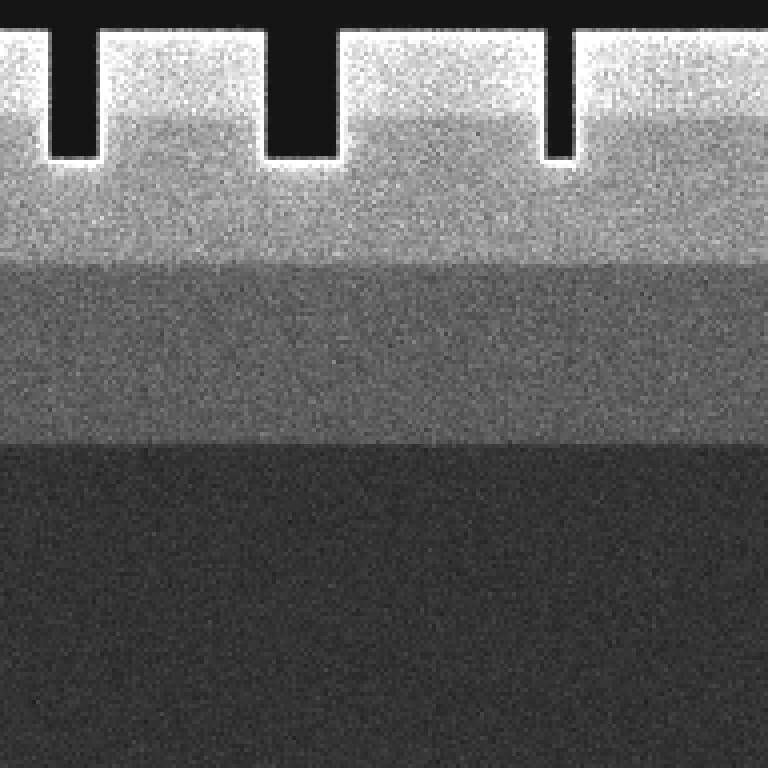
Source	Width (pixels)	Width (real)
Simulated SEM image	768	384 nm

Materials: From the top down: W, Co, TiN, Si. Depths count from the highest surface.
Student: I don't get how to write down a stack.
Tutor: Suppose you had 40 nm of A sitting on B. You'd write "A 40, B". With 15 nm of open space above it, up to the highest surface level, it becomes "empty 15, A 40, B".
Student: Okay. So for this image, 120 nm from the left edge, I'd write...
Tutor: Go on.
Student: W 42, Co 74, TiN 90, Si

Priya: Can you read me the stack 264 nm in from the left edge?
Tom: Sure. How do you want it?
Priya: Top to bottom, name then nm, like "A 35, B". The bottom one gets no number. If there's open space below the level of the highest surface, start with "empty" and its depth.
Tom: W 42, Co 74, TiN 90, Si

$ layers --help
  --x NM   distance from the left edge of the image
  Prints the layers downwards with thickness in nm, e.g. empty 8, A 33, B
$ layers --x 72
W 42, Co 74, TiN 90, Si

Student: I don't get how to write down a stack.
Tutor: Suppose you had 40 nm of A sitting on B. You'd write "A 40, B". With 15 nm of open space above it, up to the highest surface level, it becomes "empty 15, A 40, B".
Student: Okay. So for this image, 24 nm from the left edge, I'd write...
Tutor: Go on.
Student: empty 64, Co 52, TiN 90, Si